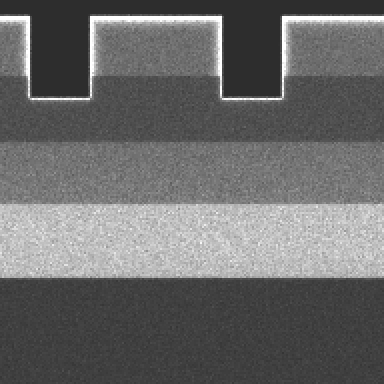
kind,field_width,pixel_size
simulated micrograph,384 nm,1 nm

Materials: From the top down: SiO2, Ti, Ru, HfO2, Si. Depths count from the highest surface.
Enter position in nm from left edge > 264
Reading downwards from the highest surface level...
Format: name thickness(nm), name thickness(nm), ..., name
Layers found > empty 82, Ti 44, Ru 62, HfO2 74, Si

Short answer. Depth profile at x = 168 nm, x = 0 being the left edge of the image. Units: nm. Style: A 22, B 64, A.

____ SiO2 60, Ti 66, Ru 62, HfO2 74, Si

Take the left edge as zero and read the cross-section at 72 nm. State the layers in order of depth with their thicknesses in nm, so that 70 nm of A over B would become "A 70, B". empty 82, Ti 44, Ru 62, HfO2 74, Si